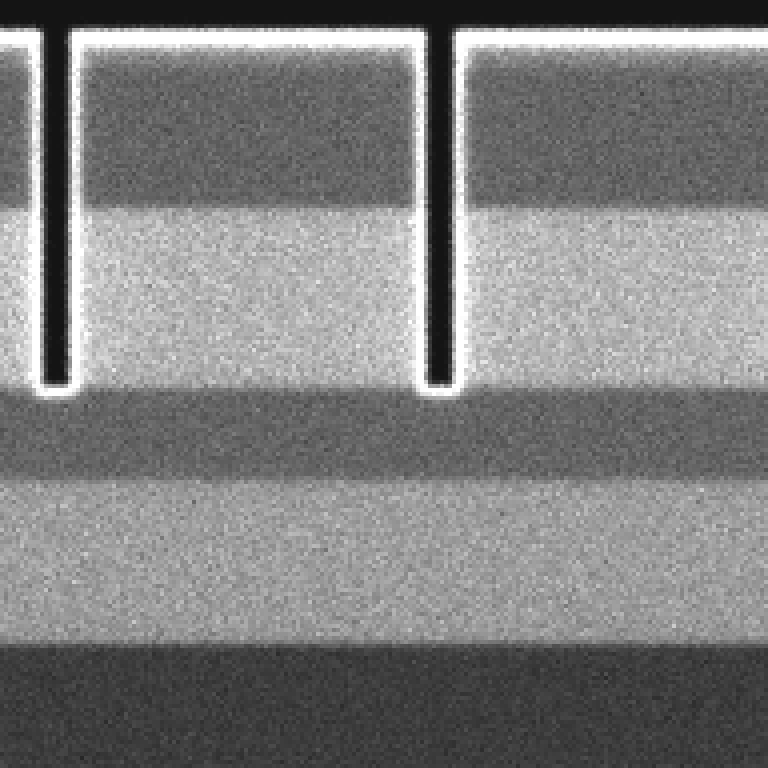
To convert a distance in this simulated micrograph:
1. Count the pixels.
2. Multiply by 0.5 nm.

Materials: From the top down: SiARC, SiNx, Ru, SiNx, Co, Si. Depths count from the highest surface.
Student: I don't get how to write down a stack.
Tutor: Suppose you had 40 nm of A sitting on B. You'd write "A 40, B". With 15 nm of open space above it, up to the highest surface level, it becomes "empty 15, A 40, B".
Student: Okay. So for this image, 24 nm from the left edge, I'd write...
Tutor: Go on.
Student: empty 178, SiNx 46, Co 82, Si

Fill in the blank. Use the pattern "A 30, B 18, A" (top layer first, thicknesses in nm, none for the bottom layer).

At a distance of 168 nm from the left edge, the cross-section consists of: SiARC 18, SiNx 70, Ru 90, SiNx 46, Co 82, Si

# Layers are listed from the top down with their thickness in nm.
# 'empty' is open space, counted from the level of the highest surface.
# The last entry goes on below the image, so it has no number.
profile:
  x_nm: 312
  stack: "SiARC 18, SiNx 70, Ru 90, SiNx 46, Co 82, Si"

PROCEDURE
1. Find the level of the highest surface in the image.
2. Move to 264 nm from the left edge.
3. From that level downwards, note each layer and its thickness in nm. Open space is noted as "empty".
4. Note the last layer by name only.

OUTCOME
SiARC 18, SiNx 70, Ru 90, SiNx 46, Co 82, Si